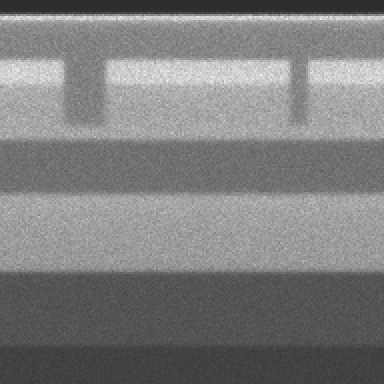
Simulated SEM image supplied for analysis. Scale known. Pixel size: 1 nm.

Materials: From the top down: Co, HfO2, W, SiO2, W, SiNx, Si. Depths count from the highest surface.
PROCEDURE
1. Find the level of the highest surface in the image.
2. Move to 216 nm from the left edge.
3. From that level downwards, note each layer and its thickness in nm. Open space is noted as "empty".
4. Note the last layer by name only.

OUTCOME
Co 44, HfO2 24, W 56, SiO2 54, W 78, SiNx 74, Si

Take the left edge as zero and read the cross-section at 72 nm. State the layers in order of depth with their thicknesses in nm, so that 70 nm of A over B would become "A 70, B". Co 110, W 14, SiO2 54, W 78, SiNx 74, Si